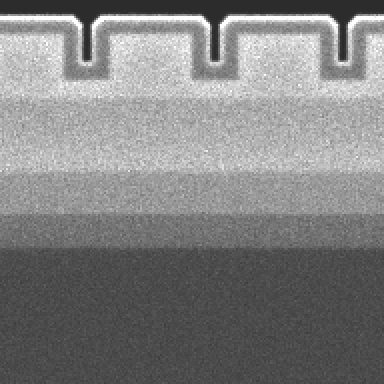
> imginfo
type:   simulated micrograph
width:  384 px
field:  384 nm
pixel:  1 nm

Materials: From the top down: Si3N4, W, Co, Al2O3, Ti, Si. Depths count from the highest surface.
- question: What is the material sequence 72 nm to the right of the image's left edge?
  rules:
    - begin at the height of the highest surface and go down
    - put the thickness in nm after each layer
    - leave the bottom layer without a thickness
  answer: Si3N4 64, W 18, Co 74, Al2O3 42, Ti 34, Si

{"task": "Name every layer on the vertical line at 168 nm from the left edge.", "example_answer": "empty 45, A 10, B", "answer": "Si3N4 18, W 64, Co 74, Al2O3 42, Ti 34, Si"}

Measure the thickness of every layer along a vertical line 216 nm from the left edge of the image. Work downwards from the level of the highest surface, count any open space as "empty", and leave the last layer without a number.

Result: empty 46, Si3N4 18, W 18, Co 74, Al2O3 42, Ti 34, Si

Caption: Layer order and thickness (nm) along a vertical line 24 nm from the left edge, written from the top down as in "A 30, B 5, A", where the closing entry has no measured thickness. Si3N4 18, W 64, Co 74, Al2O3 42, Ti 34, Si